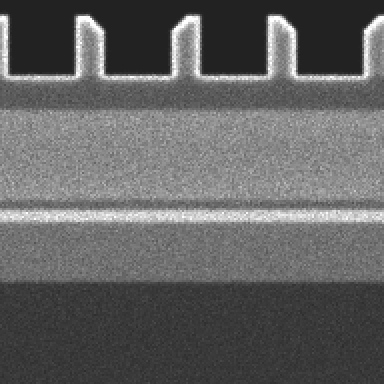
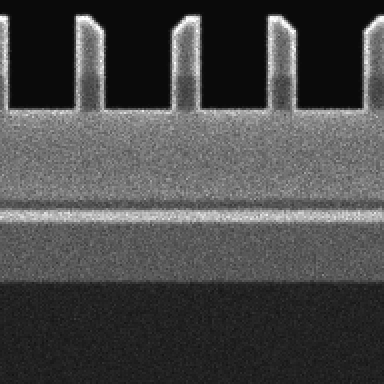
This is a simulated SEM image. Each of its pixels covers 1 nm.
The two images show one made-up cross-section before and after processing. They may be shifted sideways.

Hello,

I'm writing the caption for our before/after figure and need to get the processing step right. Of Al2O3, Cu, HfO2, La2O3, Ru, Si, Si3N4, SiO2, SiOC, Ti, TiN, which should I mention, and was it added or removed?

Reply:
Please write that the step removed Si3N4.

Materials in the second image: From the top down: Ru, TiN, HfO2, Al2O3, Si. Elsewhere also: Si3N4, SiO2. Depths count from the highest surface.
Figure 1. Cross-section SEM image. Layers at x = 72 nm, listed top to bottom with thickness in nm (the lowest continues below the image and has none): empty 94, Ru 90, TiN 10, HfO2 12, Al2O3 60, Si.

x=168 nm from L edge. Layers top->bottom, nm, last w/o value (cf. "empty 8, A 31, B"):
empty 94, Ru 90, TiN 10, HfO2 12, Al2O3 60, Si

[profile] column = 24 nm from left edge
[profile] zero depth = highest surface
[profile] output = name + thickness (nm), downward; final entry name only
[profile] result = empty 94, Ru 90, TiN 10, HfO2 12, Al2O3 60, Si